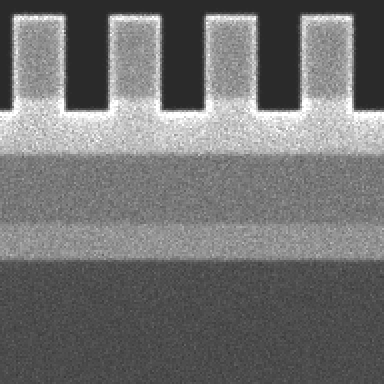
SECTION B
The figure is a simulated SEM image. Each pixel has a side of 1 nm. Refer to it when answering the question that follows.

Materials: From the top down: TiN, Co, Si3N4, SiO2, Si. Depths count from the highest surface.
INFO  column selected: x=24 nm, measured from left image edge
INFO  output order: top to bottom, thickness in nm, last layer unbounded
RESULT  TiN 82, Co 56, Si3N4 70, SiO2 36, Si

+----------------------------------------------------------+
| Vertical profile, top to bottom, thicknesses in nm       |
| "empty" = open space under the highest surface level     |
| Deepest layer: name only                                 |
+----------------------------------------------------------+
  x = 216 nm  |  TiN 82, Co 56, Si3N4 70, SiO2 36, Si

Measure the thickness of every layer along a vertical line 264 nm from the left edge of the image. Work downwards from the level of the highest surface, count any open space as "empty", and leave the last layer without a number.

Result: empty 96, Co 42, Si3N4 70, SiO2 36, Si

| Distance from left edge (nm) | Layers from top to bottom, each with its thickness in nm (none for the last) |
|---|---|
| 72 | empty 96, Co 42, Si3N4 70, SiO2 36, Si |